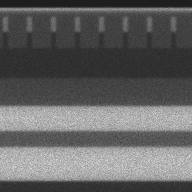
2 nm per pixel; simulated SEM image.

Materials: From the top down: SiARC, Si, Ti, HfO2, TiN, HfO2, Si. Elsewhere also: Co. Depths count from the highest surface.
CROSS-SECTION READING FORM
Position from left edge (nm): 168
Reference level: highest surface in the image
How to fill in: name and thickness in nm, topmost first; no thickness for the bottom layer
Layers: SiARC 80, Si 60, Ti 56, HfO2 50, TiN 32, HfO2 68, Si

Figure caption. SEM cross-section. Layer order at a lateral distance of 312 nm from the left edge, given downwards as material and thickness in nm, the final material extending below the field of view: SiARC 80, Si 60, Ti 56, HfO2 50, TiN 32, HfO2 68, Si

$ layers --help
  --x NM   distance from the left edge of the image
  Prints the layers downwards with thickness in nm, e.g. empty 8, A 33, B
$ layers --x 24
SiARC 80, Si 60, Ti 56, HfO2 50, TiN 32, HfO2 68, Si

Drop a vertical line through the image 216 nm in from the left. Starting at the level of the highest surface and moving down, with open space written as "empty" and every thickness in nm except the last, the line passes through SiARC 80, Si 60, Ti 56, HfO2 50, TiN 32, HfO2 68, Si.